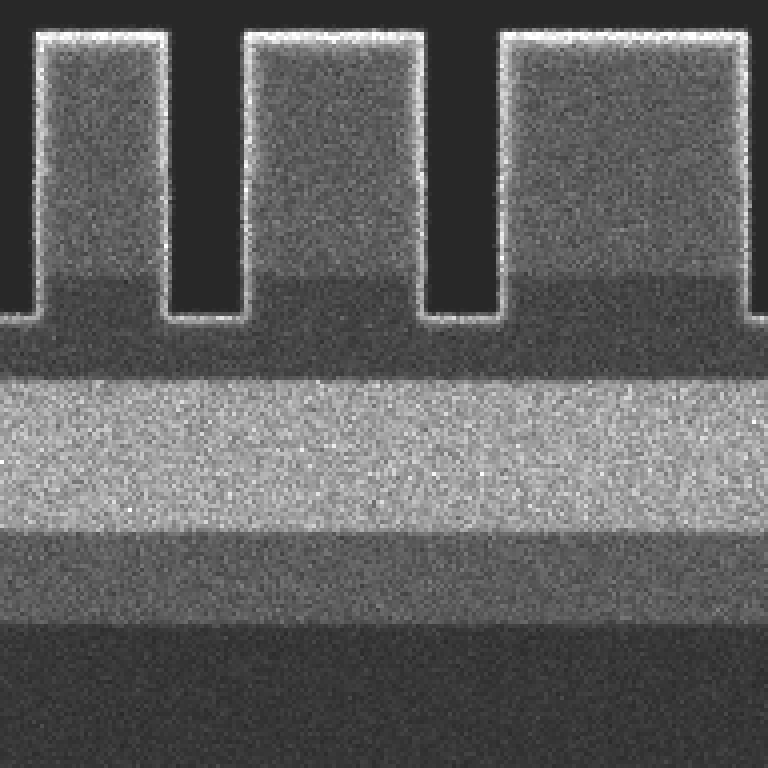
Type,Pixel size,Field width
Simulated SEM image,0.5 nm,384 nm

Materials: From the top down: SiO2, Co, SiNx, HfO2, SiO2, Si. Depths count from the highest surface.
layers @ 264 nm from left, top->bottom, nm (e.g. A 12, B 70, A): SiO2 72, Co 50, SiNx 52, HfO2 76, SiO2 46, Si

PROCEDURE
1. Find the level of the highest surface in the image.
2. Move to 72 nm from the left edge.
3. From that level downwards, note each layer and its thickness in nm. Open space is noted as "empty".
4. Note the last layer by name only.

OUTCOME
SiO2 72, Co 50, SiNx 52, HfO2 76, SiO2 46, Si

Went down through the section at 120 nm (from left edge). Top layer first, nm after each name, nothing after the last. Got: empty 142, SiNx 32, HfO2 76, SiO2 46, Si